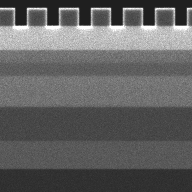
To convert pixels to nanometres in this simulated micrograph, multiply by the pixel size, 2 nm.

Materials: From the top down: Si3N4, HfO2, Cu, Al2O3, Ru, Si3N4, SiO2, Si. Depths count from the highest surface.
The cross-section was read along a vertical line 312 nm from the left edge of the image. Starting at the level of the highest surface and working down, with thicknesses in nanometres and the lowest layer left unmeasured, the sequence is Si3N4 36, HfO2 48, Cu 26, Al2O3 26, Ru 62, Si3N4 68, SiO2 56, Si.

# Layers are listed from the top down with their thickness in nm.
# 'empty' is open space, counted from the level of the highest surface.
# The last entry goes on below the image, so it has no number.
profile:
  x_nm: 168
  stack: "empty 36, HfO2 48, Cu 26, Al2O3 26, Ru 62, Si3N4 68, SiO2 56, Si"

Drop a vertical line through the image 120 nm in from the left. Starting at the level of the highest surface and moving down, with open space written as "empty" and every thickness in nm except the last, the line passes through Si3N4 36, HfO2 48, Cu 26, Al2O3 26, Ru 62, Si3N4 68, SiO2 56, Si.